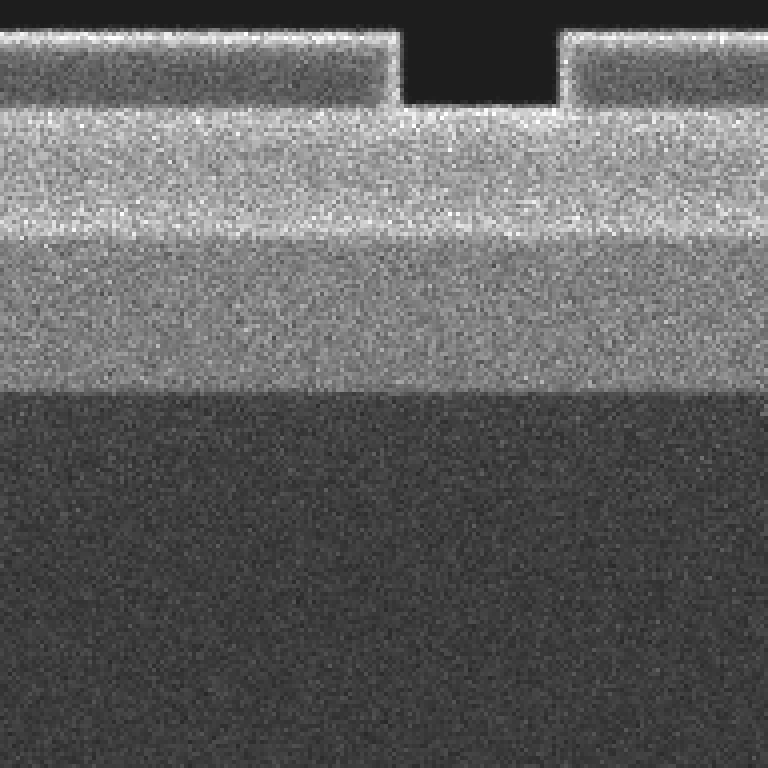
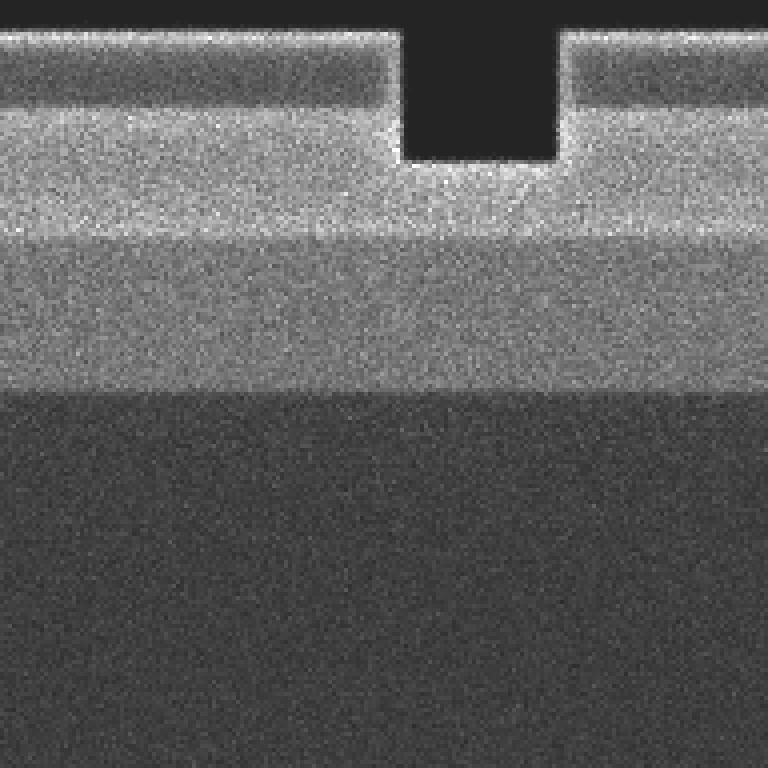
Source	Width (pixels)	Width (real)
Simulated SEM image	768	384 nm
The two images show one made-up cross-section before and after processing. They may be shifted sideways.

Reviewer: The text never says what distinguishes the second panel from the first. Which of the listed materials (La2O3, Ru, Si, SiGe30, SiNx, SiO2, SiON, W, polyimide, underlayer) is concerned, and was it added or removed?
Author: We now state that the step removed W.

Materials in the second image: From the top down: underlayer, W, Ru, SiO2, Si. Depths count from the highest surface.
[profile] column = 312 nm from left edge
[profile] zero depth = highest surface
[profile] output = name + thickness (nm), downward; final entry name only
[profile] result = underlayer 38, W 48, Ru 16, SiO2 78, Si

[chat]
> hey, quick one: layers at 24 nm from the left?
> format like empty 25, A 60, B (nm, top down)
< underlayer 38, W 48, Ru 16, SiO2 78, Si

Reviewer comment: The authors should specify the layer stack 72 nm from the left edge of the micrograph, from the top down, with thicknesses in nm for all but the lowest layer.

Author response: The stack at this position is underlayer 38, W 48, Ru 16, SiO2 78, Si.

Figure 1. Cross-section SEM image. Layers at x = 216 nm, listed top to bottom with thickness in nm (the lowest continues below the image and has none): empty 66, W 20, Ru 16, SiO2 78, Si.